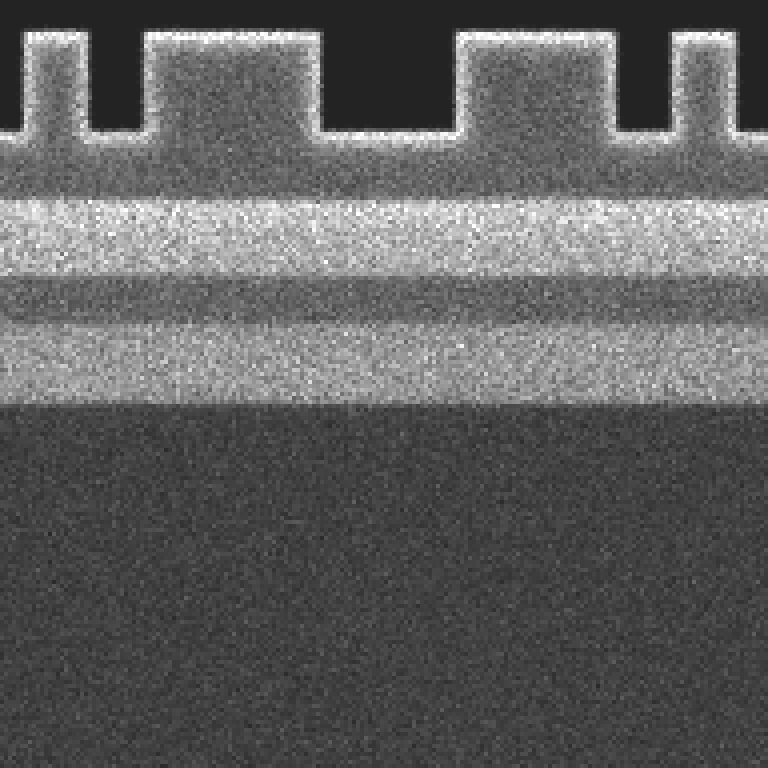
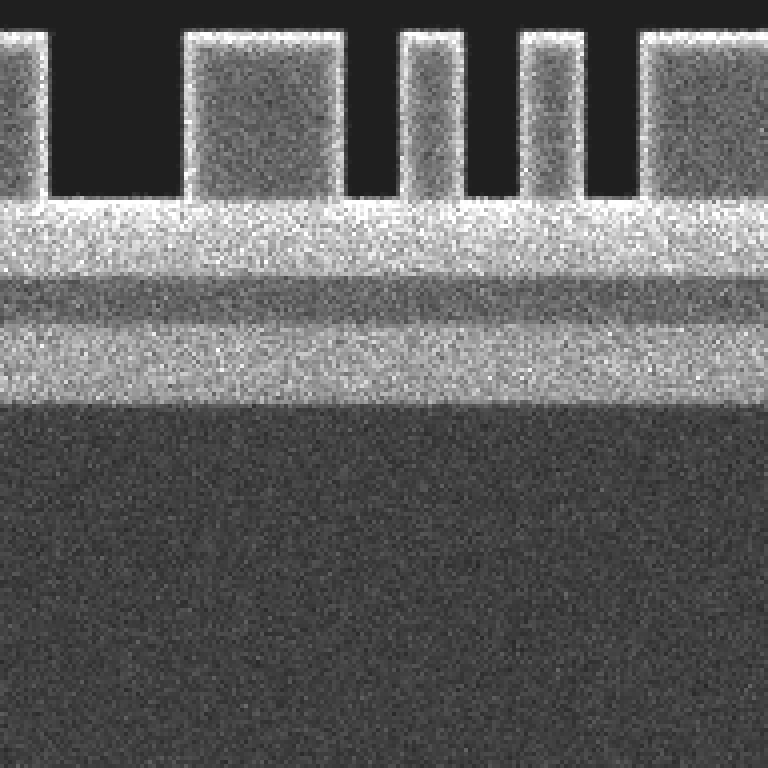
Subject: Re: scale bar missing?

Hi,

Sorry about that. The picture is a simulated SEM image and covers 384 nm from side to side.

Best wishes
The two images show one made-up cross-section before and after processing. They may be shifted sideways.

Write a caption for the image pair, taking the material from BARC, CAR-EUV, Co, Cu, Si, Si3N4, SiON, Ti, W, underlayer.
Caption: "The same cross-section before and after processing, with underlayer removed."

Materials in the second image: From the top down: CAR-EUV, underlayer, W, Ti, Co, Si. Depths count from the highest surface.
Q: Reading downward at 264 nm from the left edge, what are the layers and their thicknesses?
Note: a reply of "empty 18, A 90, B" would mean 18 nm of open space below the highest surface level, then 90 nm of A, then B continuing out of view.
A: CAR-EUV 50, underlayer 34, W 38, Ti 24, Co 40, Si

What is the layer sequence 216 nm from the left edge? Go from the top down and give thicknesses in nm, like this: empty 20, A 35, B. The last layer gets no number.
CAR-EUV 50, underlayer 34, W 38, Ti 24, Co 40, Si